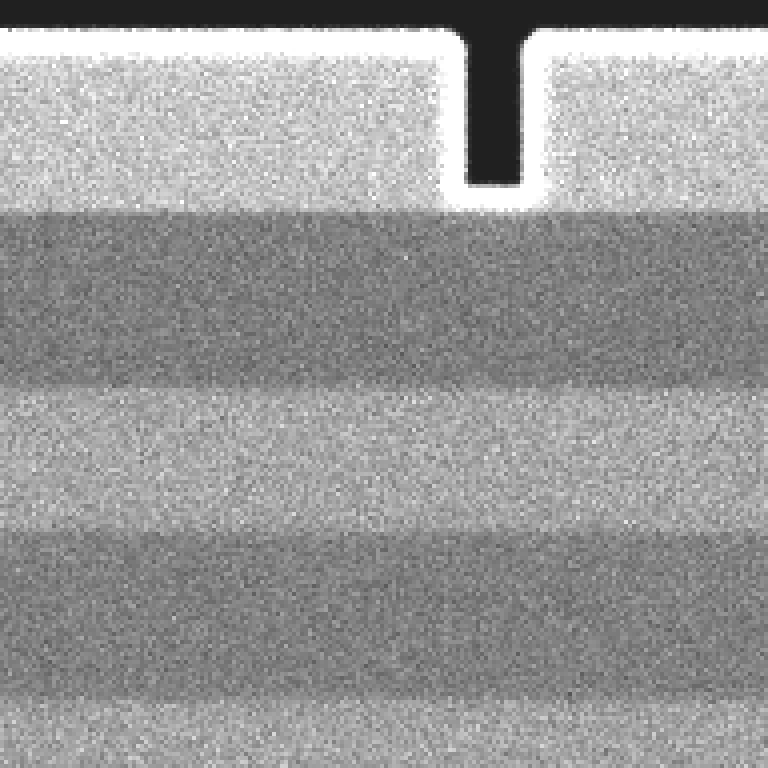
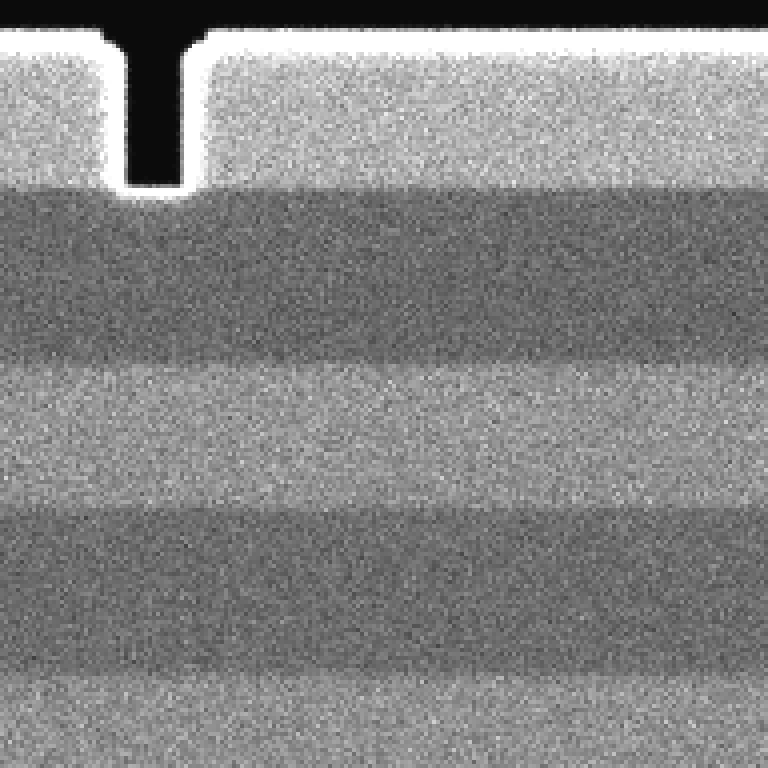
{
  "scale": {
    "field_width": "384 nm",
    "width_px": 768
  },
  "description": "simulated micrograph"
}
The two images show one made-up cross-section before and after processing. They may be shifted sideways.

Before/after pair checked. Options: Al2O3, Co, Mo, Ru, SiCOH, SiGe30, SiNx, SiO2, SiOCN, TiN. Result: removed Al2O3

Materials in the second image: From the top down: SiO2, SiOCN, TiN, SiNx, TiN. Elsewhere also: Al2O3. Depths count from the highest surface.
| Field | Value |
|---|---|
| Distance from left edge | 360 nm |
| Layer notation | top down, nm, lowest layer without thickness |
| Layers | SiO2 78, SiOCN 88, TiN 72, SiNx 84, TiN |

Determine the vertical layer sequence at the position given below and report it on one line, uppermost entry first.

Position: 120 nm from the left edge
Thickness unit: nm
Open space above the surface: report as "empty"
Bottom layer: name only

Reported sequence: SiO2 78, SiOCN 88, TiN 72, SiNx 84, TiN